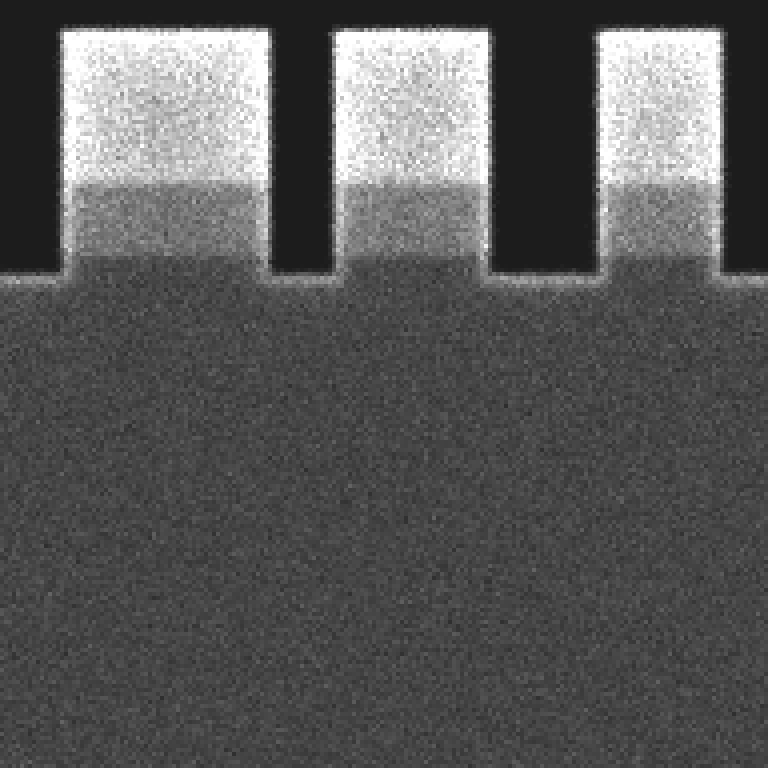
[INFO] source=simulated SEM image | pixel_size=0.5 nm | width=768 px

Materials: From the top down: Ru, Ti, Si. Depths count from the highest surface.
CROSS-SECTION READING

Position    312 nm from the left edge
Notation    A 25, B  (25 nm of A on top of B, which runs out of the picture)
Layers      Ru 76, Ti 36, Si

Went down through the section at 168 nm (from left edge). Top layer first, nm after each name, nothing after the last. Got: Ru 76, Ti 36, Si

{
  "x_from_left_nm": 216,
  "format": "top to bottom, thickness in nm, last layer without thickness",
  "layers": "Ru 76, Ti 36, Si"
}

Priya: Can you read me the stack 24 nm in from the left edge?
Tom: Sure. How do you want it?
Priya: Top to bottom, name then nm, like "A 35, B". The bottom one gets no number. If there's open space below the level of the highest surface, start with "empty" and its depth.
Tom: empty 122, Si